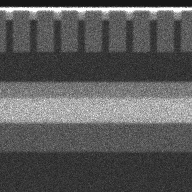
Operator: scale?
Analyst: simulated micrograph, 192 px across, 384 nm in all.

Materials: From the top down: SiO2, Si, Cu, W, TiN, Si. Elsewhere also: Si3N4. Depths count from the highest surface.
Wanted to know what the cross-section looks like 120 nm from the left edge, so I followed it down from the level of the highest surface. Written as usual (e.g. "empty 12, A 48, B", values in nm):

SiO2 24, Si 124, Cu 32, W 50, TiN 58, Si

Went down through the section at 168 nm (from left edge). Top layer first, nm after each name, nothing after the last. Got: SiO2 24, Si 124, Cu 32, W 50, TiN 58, Si